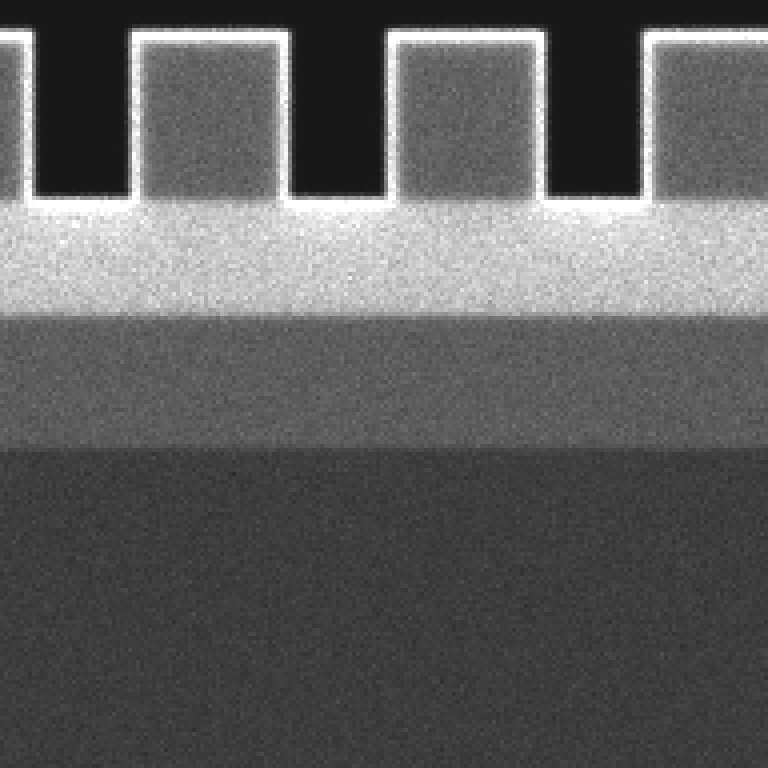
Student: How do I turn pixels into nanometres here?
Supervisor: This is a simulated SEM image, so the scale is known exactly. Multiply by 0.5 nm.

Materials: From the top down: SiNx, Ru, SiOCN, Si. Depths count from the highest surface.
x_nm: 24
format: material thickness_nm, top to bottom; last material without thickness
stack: empty 84, Ru 58, SiOCN 66, Si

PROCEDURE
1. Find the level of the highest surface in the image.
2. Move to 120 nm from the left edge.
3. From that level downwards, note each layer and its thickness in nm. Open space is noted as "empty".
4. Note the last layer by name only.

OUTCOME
SiNx 84, Ru 58, SiOCN 66, Si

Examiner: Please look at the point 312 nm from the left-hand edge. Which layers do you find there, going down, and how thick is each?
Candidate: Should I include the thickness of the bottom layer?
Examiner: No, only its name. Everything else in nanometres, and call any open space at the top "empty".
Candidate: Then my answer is empty 84, Ru 58, SiOCN 66, Si